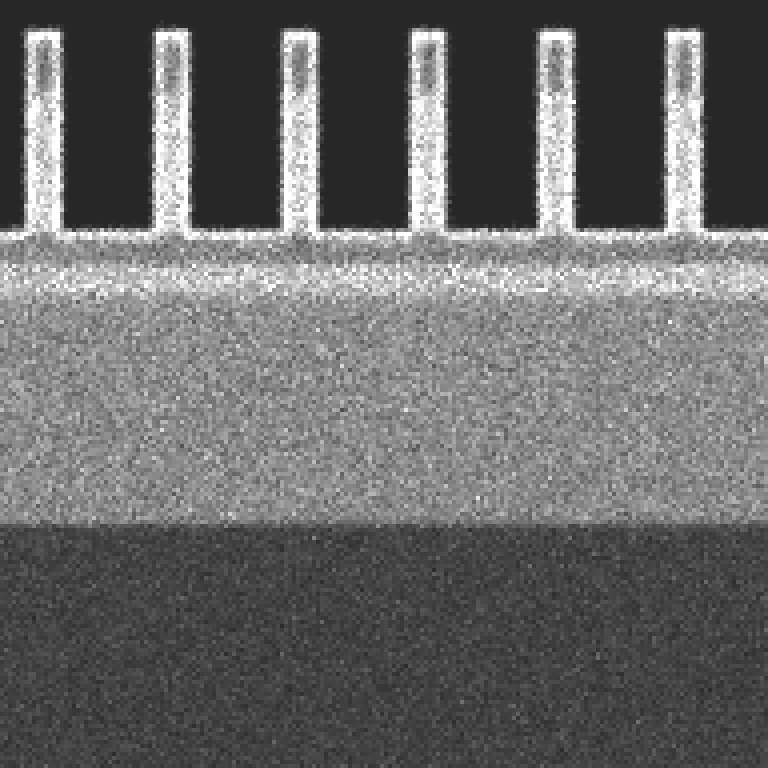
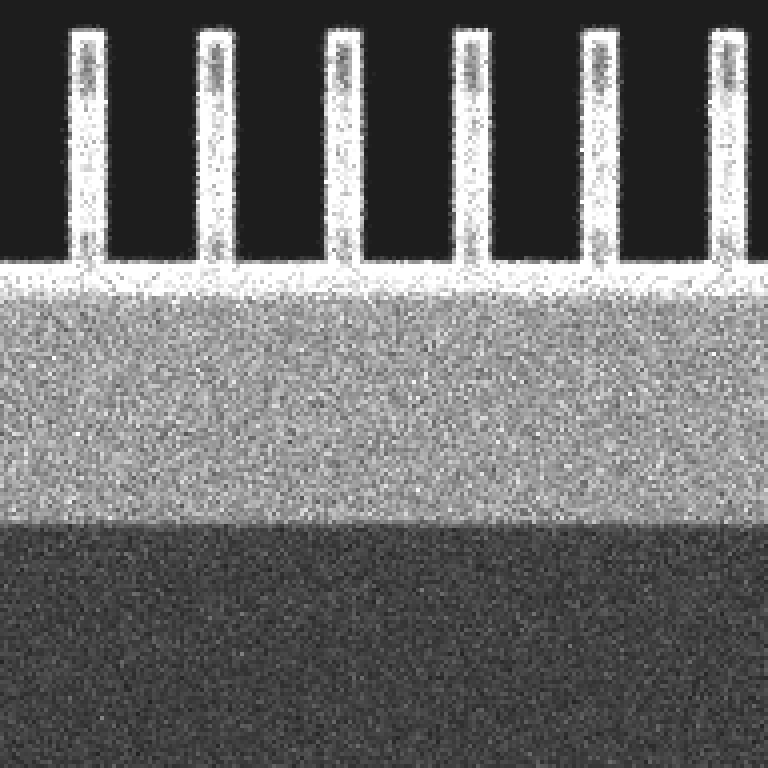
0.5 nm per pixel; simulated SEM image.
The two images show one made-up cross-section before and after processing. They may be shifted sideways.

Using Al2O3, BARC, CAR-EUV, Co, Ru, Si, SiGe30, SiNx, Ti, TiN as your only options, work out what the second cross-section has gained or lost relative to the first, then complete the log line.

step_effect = removed TiN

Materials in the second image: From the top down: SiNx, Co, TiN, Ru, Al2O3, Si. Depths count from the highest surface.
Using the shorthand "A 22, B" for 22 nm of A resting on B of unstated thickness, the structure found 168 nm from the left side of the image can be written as SiNx 30, Co 70, TiN 16, Ru 16, Al2O3 114, Si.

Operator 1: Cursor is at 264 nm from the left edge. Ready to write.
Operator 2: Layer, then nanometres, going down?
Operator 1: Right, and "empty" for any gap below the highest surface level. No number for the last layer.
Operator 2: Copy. empty 116, Ru 16, Al2O3 114, Si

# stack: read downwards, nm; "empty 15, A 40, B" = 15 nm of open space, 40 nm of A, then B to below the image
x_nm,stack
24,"empty 116, Ru 16, Al2O3 114, Si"